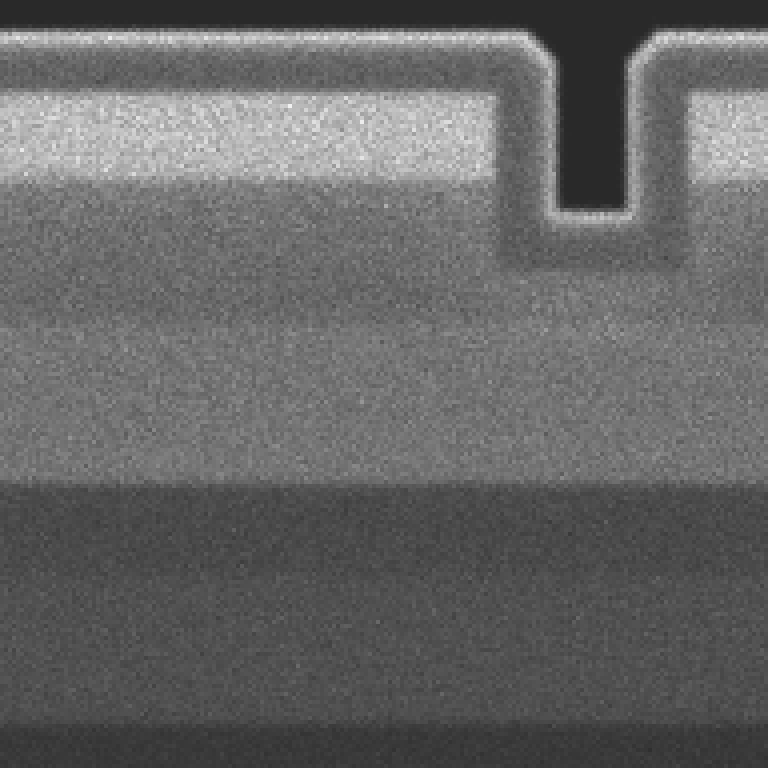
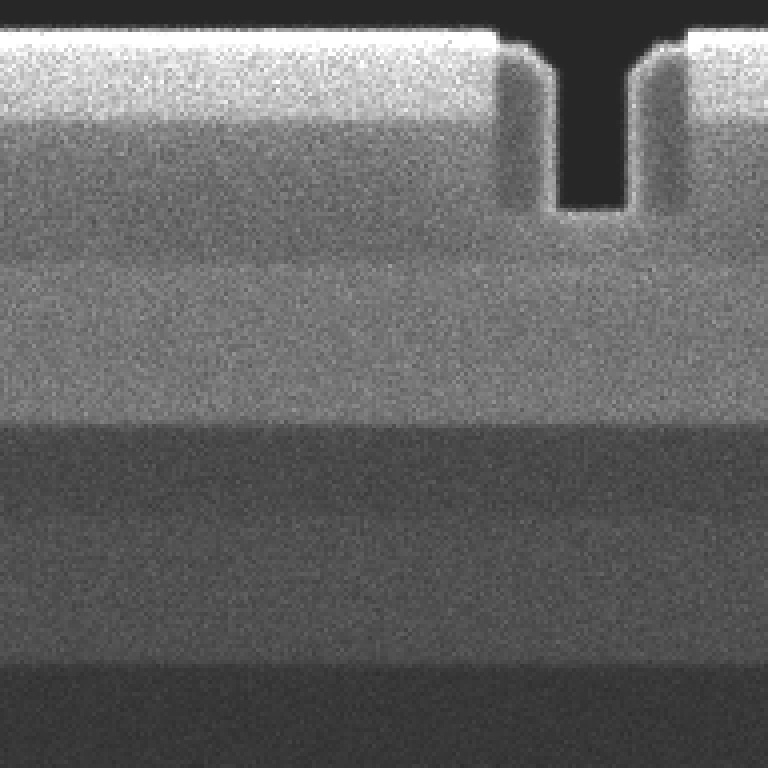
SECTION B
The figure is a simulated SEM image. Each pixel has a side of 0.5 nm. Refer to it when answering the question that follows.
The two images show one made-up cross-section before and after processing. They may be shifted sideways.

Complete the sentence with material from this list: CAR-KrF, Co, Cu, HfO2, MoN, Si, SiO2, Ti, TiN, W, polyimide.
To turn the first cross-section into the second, SiO2 must be removed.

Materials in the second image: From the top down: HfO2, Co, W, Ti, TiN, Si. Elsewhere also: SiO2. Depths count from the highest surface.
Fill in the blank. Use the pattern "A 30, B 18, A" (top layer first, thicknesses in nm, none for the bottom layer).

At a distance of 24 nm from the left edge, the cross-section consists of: HfO2 44, Co 72, W 80, Ti 46, TiN 74, Si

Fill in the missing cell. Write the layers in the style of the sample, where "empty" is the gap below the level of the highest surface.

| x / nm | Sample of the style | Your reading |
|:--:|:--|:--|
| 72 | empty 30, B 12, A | HfO2 44, Co 72, W 80, Ti 46, TiN 74, Si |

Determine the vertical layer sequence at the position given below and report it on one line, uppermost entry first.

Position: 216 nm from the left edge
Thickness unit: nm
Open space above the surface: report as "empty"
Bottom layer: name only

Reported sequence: HfO2 44, Co 72, W 80, Ti 46, TiN 74, Si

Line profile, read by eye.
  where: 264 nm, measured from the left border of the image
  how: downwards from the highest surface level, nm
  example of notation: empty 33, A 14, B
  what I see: empty 8, SiO2 82, Co 26, W 80, Ti 46, TiN 74, Si